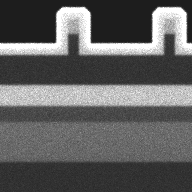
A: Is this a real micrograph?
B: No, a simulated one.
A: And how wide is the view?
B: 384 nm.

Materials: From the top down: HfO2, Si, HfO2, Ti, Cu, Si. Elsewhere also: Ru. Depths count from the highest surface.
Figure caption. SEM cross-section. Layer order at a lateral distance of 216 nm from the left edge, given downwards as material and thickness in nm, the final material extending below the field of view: empty 72, HfO2 22, Si 60, HfO2 42, Ti 32, Cu 80, Si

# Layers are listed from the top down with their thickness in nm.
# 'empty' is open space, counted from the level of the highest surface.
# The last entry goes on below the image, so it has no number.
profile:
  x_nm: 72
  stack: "empty 72, HfO2 22, Si 60, HfO2 42, Ti 32, Cu 80, Si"